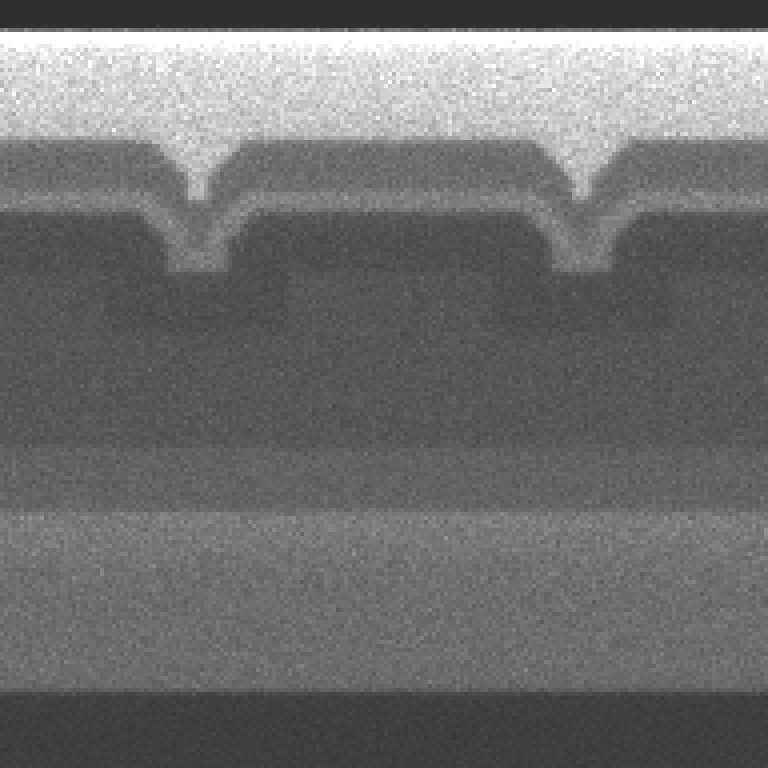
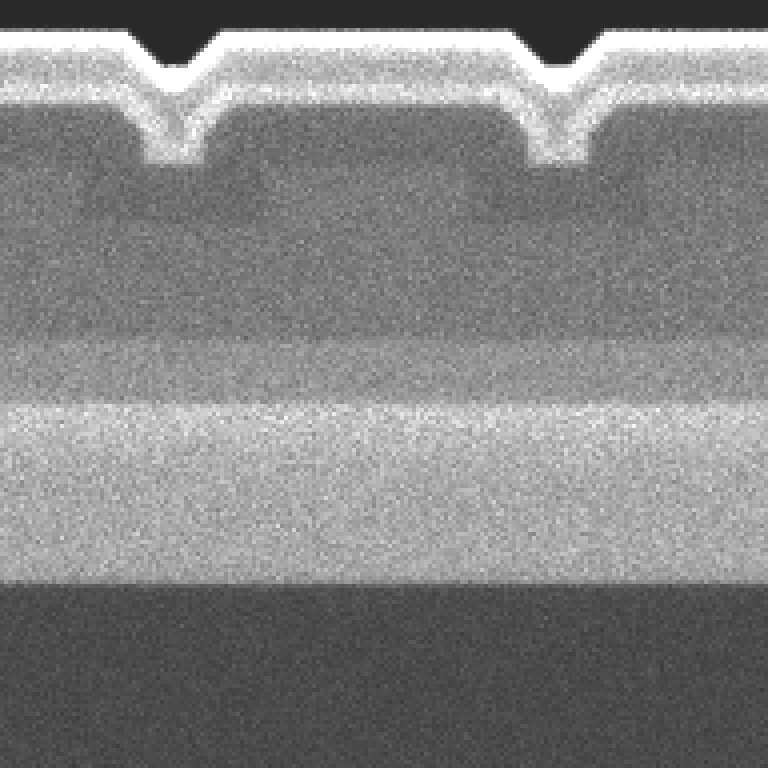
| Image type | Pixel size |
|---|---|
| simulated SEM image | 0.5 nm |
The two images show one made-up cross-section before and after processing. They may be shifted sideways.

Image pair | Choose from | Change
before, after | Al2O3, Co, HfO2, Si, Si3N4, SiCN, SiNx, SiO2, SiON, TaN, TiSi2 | HfO2 (removed)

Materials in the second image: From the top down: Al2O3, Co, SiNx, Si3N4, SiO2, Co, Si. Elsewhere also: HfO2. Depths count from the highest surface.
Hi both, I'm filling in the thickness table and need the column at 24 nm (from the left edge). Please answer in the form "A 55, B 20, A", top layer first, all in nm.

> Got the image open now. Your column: Al2O3 26, Co 10, SiNx 30, Si3N4 88, SiO2 32, Co 90, Si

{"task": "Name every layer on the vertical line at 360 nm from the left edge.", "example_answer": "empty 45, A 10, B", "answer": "Al2O3 26, Co 10, SiNx 30, Si3N4 88, SiO2 32, Co 90, Si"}